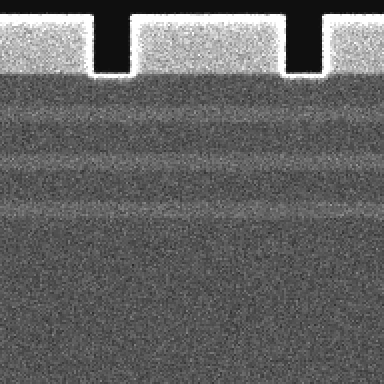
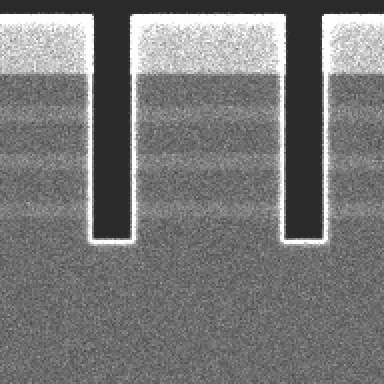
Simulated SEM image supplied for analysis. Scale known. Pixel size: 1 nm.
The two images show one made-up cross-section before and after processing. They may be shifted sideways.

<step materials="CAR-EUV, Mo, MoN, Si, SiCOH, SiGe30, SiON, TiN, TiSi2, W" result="removed Si and SiGe30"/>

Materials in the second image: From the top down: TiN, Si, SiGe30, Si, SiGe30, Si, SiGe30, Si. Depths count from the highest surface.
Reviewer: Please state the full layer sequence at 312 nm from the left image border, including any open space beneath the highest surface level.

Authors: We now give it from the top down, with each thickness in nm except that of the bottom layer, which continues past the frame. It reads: empty 224, Si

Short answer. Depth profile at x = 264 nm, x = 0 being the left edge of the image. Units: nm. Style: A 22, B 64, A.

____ TiN 58, Si 32, SiGe30 16, Si 32, SiGe30 16, Si 32, SiGe30 16, Si